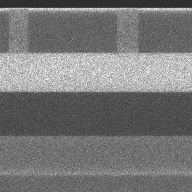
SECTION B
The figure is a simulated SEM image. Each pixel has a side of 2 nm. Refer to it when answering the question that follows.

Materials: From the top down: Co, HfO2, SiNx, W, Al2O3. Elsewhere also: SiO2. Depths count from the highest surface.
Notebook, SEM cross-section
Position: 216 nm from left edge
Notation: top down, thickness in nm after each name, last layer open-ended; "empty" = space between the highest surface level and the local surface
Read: SiO2 90, HfO2 78, SiNx 88, W 78, Al2O3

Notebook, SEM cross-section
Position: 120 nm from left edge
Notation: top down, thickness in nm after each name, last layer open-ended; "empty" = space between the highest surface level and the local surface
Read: SiO2 90, HfO2 78, SiNx 88, W 78, Al2O3